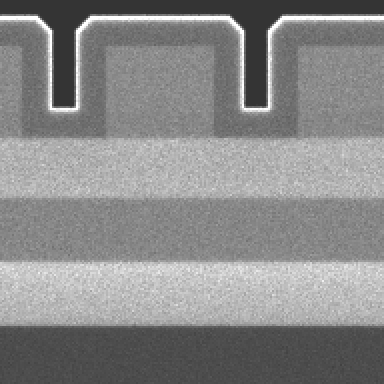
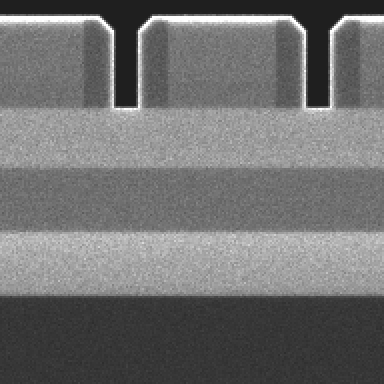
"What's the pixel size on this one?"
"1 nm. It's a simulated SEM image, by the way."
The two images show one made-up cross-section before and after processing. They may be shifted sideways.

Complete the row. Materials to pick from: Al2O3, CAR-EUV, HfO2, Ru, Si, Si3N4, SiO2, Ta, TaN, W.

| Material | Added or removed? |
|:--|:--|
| Si3N4 | removed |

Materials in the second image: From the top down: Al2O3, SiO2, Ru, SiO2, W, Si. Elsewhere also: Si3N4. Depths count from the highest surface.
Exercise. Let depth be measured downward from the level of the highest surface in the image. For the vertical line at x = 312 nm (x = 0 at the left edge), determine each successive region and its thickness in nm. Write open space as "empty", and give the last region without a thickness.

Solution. empty 92, Ru 60, SiO2 64, W 64, Si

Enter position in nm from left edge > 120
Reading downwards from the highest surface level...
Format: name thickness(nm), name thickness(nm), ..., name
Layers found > empty 92, Ru 60, SiO2 64, W 64, Si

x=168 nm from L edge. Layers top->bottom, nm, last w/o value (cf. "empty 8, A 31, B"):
Al2O3 66, SiO2 26, Ru 60, SiO2 64, W 64, Si